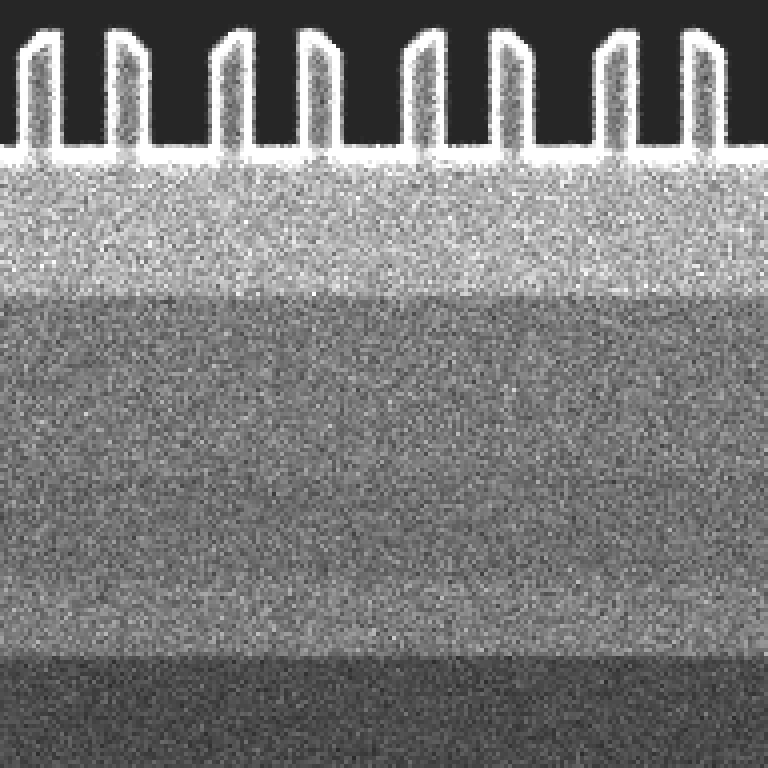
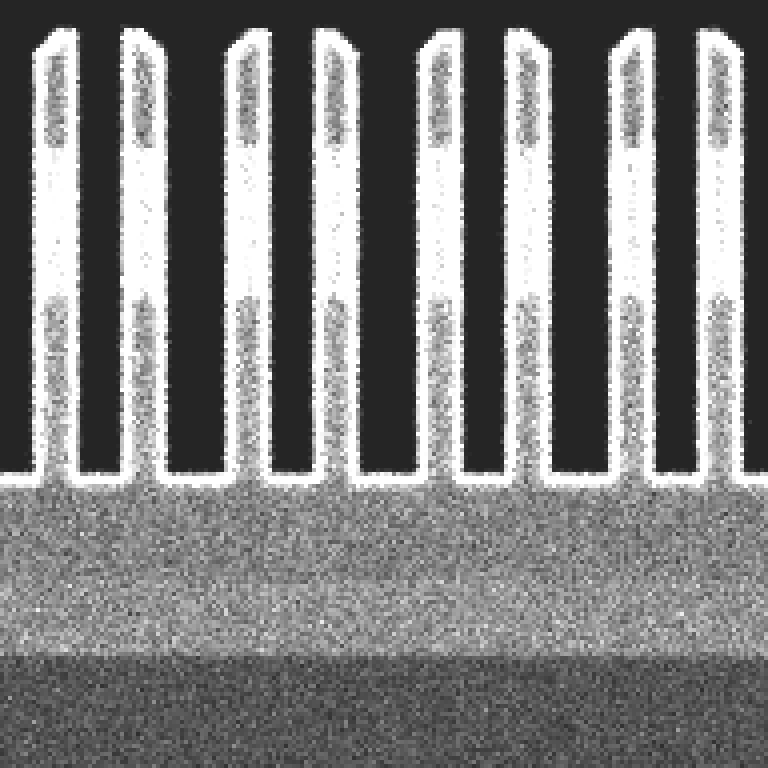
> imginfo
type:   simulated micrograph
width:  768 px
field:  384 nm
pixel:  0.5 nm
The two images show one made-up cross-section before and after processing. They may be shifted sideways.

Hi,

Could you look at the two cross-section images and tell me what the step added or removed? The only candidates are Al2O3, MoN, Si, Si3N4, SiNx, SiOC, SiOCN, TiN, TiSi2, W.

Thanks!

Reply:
removed Al2O3 and TiN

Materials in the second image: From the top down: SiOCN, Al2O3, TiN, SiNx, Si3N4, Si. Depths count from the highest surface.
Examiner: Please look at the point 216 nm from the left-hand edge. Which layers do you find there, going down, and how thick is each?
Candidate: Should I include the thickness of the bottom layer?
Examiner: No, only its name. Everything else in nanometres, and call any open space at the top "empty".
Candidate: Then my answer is empty 4, SiOCN 54, Al2O3 74, TiN 90, SiNx 52, Si3N4 38, Si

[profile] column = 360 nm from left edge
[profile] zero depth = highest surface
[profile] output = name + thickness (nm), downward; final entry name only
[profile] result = empty 2, SiOCN 56, Al2O3 74, TiN 90, SiNx 52, Si3N4 38, Si